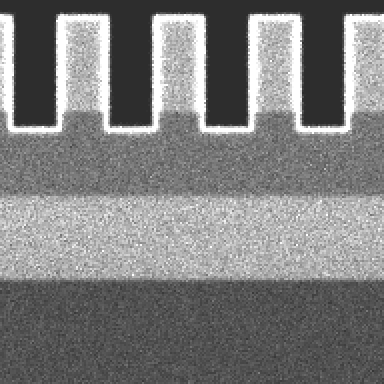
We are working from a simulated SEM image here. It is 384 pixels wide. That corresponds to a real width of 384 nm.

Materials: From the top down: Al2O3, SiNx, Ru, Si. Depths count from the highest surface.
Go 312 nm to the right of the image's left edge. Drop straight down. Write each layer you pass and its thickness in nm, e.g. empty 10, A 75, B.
empty 112, SiNx 68, Ru 84, Si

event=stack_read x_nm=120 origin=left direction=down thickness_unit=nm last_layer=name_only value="empty 112, SiNx 68, Ru 84, Si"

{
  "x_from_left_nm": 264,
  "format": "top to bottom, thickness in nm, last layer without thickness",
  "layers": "Al2O3 96, SiNx 84, Ru 84, Si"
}